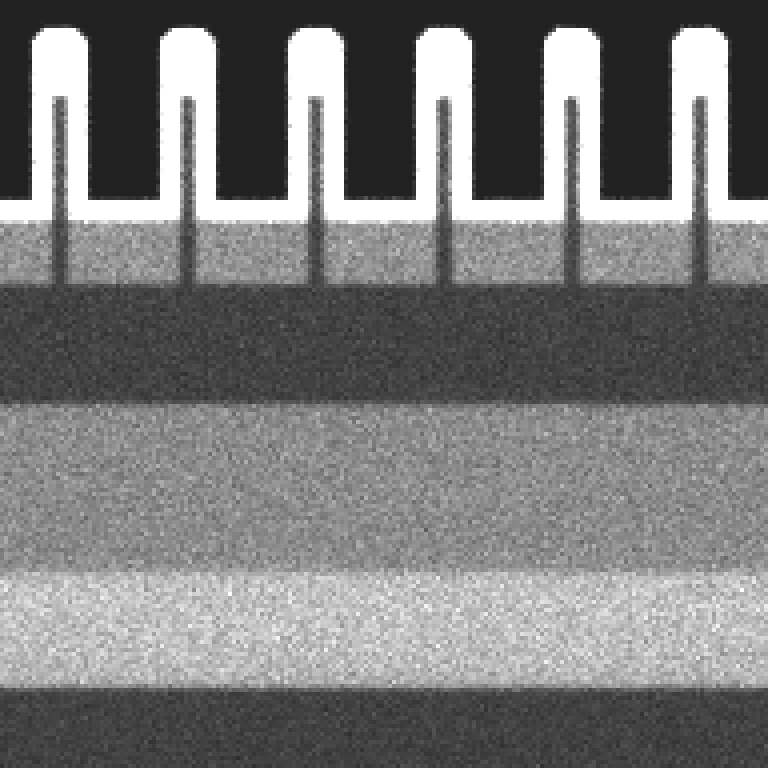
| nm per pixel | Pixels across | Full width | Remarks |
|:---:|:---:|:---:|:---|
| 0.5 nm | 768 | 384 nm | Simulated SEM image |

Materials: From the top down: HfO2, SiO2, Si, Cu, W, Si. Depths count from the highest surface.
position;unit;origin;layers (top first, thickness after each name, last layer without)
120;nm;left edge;empty 86, HfO2 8, SiO2 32, Si 60, Cu 84, W 58, Si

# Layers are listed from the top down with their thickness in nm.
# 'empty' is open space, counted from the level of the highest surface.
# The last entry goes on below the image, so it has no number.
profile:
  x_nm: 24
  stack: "HfO2 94, SiO2 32, Si 60, Cu 84, W 58, Si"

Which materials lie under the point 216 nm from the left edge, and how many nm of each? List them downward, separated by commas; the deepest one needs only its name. HfO2 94, SiO2 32, Si 60, Cu 84, W 58, Si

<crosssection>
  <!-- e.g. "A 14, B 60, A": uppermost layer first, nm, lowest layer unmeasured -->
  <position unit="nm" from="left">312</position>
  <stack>empty 86, HfO2 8, SiO2 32, Si 60, Cu 84, W 58, Si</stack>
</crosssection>